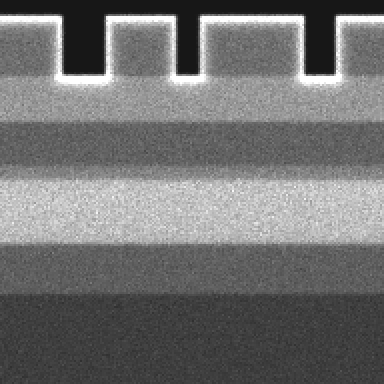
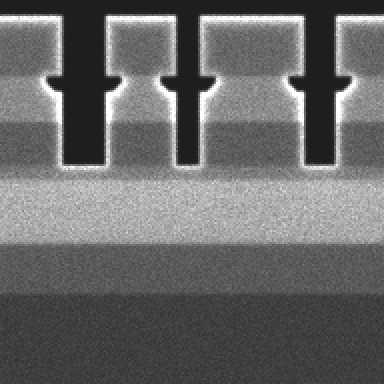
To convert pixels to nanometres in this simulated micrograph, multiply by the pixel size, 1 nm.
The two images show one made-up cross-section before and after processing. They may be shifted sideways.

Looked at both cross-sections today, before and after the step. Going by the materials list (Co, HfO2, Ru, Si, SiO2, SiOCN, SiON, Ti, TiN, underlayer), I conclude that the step removed SiO2 and SiOCN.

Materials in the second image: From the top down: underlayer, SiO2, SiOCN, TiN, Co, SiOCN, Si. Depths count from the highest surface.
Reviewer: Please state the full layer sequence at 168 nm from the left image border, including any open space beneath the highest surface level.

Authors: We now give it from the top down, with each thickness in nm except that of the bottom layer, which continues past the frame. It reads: underlayer 60, empty 16, SiO2 30, SiOCN 44, TiN 14, Co 64, SiOCN 50, Si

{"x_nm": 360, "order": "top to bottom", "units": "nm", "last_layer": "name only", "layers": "underlayer 60, SiO2 46, SiOCN 44, TiN 14, Co 64, SiOCN 50, Si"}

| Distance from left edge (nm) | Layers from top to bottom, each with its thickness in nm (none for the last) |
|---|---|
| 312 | empty 150, TiN 14, Co 64, SiOCN 50, Si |